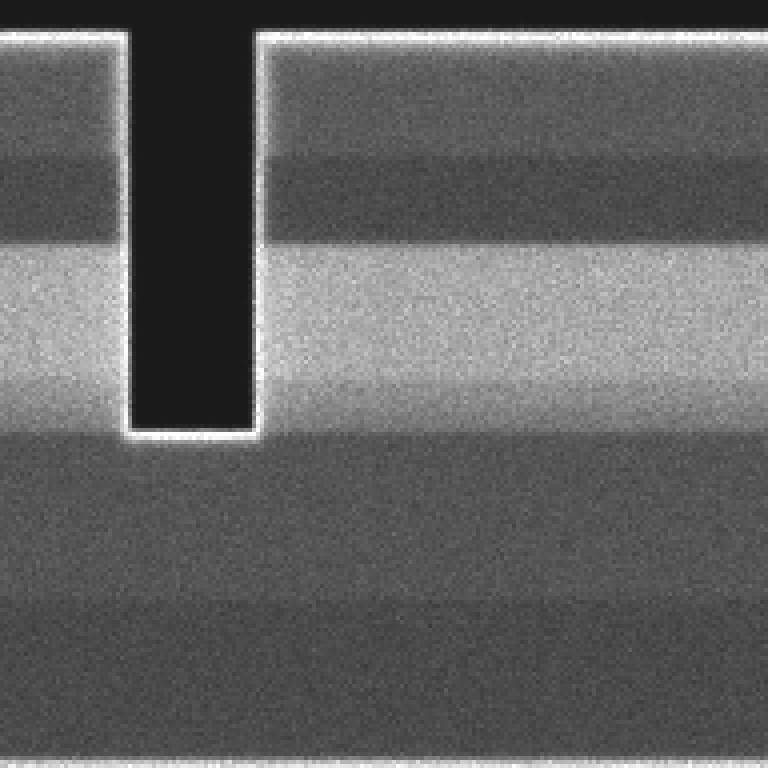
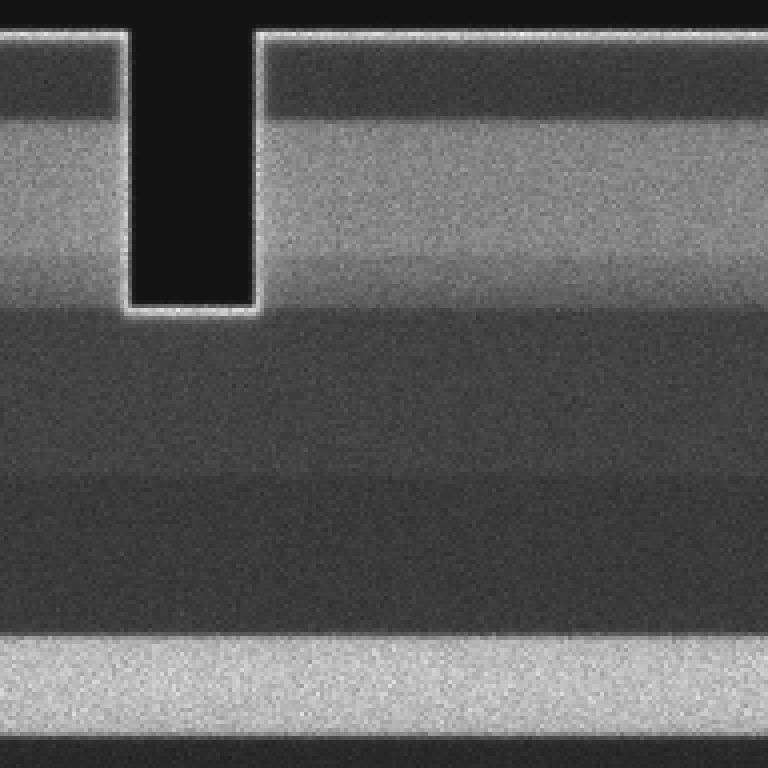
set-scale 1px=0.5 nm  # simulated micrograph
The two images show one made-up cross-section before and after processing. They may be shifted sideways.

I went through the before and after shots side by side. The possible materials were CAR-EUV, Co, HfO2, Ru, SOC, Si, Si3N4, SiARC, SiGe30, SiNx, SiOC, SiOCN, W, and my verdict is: removed, SOC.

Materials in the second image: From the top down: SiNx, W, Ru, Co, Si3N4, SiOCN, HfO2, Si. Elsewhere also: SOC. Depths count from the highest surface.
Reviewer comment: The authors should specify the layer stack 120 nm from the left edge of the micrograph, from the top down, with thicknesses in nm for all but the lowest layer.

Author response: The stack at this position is empty 138, Si3N4 84, SiOCN 80, HfO2 50, Si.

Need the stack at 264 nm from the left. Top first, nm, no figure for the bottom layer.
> SiNx 44, W 68, Ru 14, Co 12, Si3N4 84, SiOCN 80, HfO2 50, Si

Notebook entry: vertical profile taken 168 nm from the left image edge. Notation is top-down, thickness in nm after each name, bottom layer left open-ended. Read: SiNx 44, W 68, Ru 14, Co 12, Si3N4 84, SiOCN 80, HfO2 50, Si